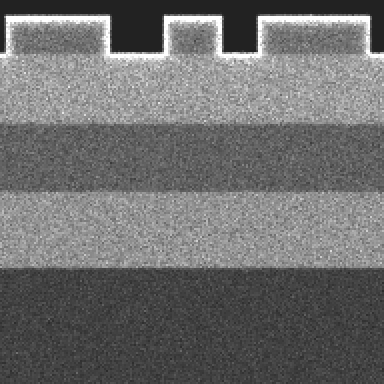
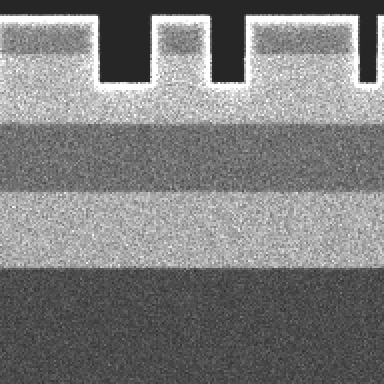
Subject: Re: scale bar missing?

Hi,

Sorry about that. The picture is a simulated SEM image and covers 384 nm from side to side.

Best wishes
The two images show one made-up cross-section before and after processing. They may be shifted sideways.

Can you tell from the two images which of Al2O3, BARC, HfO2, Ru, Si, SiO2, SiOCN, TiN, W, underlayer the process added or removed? Yes, it removed Ru.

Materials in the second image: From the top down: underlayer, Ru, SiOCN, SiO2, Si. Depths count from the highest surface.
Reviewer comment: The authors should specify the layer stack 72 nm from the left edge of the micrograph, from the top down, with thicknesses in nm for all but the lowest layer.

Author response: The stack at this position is underlayer 38, Ru 70, SiOCN 68, SiO2 76, Si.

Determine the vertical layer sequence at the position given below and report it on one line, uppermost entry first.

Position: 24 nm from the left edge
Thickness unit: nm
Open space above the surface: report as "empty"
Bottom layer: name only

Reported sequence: underlayer 38, Ru 70, SiOCN 68, SiO2 76, Si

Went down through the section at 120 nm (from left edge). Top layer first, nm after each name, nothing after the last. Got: empty 68, Ru 40, SiOCN 68, SiO2 76, Si